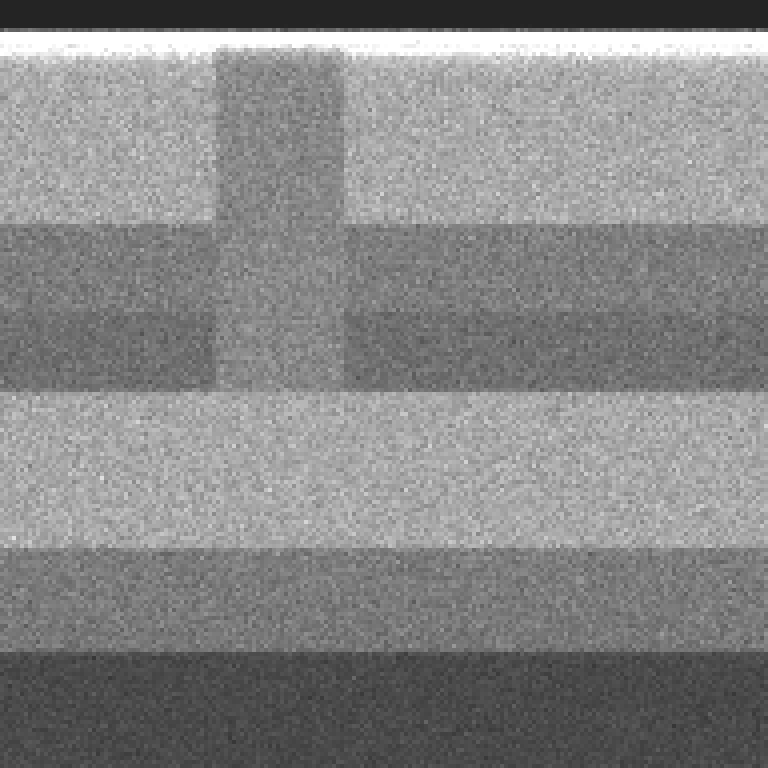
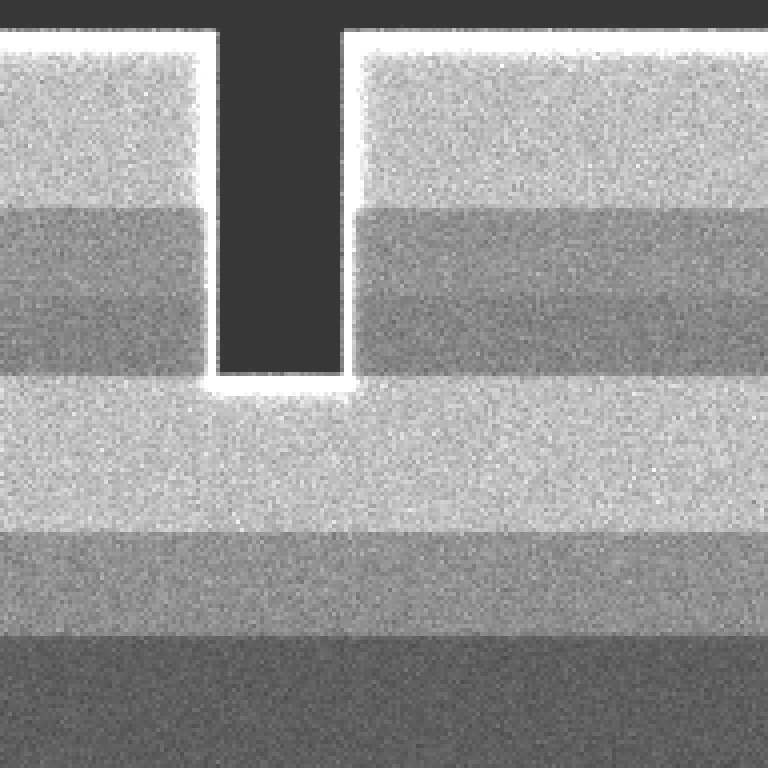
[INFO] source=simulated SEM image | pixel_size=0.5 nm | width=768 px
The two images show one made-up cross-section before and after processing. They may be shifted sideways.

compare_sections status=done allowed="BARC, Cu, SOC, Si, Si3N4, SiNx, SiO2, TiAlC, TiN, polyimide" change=removed material="SOC"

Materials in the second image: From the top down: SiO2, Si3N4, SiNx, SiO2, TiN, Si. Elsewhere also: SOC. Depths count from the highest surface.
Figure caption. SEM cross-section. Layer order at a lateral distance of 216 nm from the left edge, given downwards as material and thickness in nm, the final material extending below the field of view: SiO2 88, Si3N4 44, SiNx 40, SiO2 78, TiN 52, Si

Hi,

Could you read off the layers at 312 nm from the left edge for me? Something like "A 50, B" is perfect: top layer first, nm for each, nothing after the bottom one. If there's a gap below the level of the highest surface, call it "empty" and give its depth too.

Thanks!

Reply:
SiO2 88, Si3N4 44, SiNx 40, SiO2 78, TiN 52, Si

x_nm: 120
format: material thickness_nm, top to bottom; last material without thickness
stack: empty 172, SiO2 78, TiN 52, Si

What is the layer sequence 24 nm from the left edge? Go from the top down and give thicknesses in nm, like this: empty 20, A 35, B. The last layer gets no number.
SiO2 88, Si3N4 44, SiNx 40, SiO2 78, TiN 52, Si